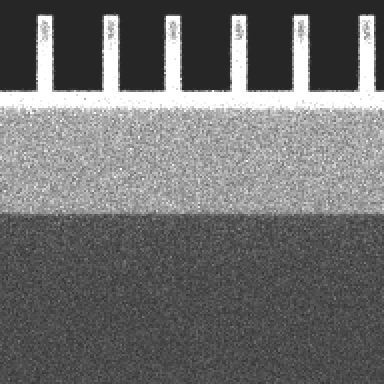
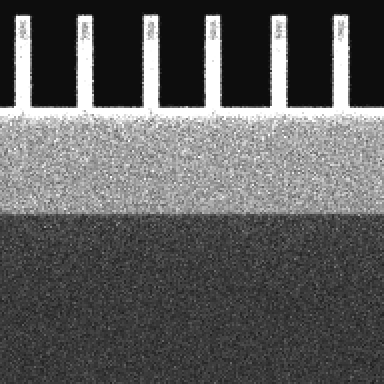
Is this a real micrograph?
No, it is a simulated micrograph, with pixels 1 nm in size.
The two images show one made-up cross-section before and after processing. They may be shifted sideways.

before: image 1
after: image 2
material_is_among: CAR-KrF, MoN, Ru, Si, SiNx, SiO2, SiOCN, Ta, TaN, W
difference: Ru, removed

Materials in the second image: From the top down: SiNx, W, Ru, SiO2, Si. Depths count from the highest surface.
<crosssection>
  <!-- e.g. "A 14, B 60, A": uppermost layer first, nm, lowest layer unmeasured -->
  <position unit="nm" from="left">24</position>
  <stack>SiNx 24, W 52, Ru 16, SiO2 106, Si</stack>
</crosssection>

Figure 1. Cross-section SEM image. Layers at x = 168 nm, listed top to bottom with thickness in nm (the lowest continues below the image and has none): empty 92, SiO2 106, Si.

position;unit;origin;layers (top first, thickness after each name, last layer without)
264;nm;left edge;empty 92, SiO2 106, Si